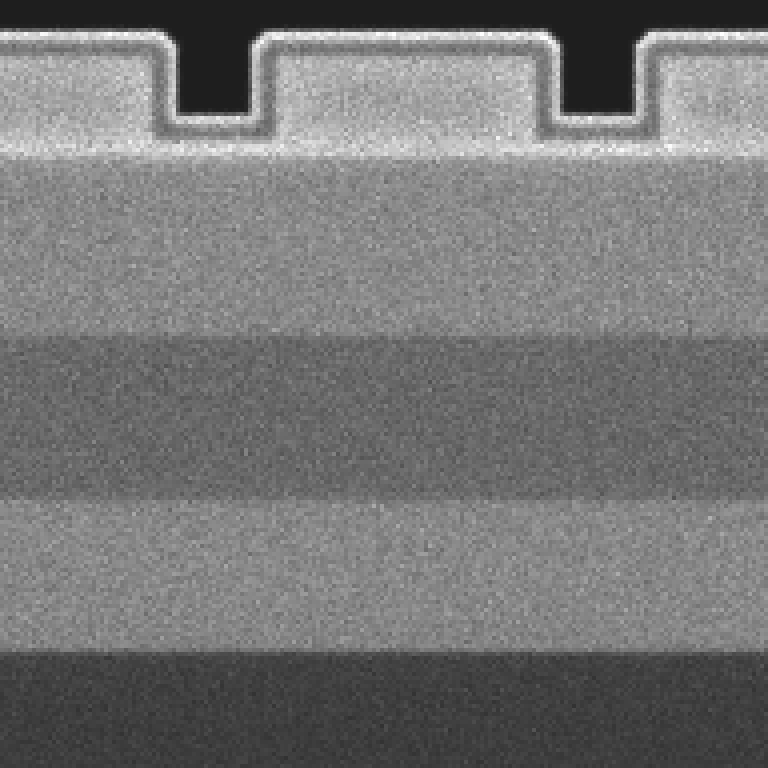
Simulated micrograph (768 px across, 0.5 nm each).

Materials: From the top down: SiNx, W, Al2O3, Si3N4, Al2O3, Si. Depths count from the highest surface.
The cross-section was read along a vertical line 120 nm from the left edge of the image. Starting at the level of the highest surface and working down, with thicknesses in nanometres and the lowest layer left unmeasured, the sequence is empty 42, SiNx 12, W 8, Al2O3 90, Si3N4 82, Al2O3 76, Si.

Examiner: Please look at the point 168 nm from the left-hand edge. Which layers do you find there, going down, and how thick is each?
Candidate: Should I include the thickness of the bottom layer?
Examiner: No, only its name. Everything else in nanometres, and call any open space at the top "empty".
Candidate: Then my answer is SiNx 12, W 50, Al2O3 90, Si3N4 82, Al2O3 76, Si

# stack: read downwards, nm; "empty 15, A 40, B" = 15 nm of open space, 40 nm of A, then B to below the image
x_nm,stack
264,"SiNx 12, W 50, Al2O3 90, Si3N4 82, Al2O3 76, Si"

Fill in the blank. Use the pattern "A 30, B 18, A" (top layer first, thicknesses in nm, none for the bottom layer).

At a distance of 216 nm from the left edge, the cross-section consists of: SiNx 12, W 50, Al2O3 90, Si3N4 82, Al2O3 76, Si